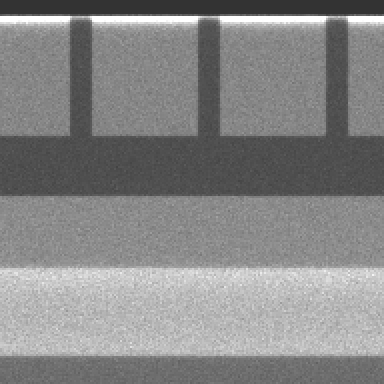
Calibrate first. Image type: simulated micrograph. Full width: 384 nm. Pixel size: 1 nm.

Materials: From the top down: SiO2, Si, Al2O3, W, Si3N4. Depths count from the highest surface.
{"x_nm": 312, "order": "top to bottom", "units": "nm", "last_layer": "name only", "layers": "SiO2 120, Si 60, Al2O3 72, W 88, Si3N4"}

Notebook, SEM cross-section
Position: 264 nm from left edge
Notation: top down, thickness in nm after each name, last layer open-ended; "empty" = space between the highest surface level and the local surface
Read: SiO2 120, Si 60, Al2O3 72, W 88, Si3N4